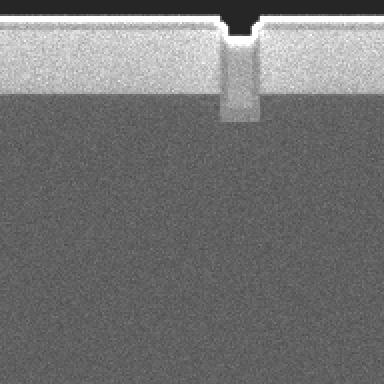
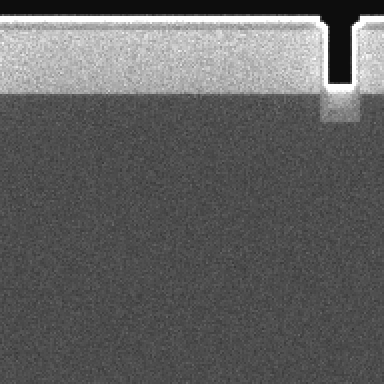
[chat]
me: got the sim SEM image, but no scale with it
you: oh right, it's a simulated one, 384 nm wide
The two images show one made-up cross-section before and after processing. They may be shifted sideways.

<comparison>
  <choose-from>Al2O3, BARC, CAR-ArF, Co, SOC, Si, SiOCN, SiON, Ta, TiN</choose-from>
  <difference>SOC removed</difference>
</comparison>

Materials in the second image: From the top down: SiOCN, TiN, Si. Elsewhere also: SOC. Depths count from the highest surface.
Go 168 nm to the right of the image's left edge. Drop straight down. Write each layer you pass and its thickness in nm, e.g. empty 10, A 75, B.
SiOCN 14, TiN 64, Si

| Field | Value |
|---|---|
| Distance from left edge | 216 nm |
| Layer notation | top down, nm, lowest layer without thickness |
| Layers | SiOCN 14, TiN 64, Si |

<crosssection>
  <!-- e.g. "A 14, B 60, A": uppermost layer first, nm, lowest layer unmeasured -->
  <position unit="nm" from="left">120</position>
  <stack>SiOCN 14, TiN 64, Si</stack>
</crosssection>